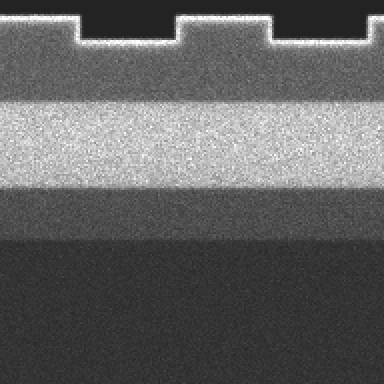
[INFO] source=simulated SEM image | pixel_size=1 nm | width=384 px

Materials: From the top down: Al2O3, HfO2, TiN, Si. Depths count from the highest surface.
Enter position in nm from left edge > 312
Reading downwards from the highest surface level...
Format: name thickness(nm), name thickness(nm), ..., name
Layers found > empty 24, Al2O3 62, HfO2 86, TiN 52, Si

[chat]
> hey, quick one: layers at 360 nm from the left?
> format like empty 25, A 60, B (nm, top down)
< empty 24, Al2O3 62, HfO2 86, TiN 52, Si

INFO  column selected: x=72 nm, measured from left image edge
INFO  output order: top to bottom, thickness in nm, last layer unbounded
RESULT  Al2O3 86, HfO2 86, TiN 52, Si